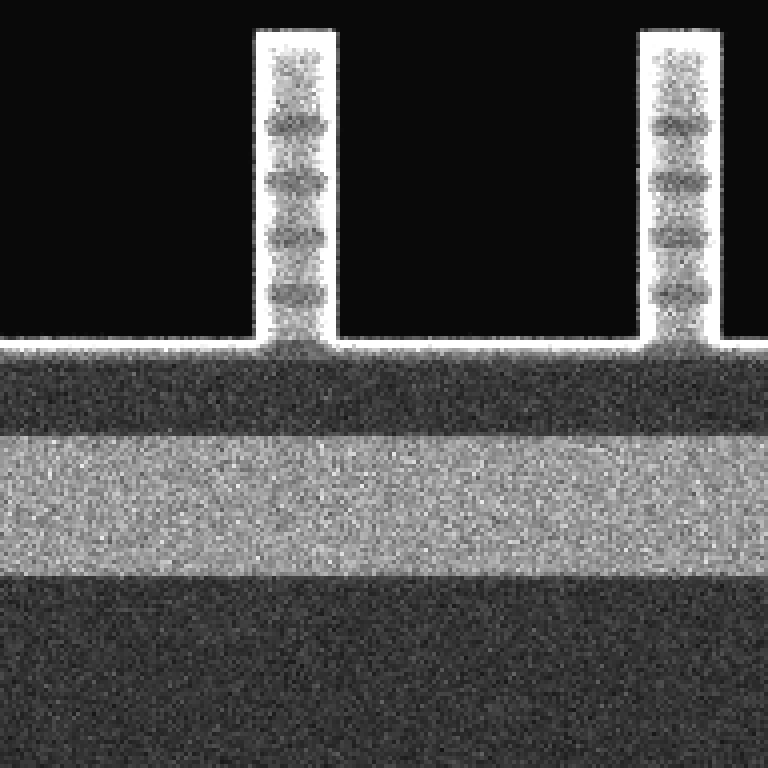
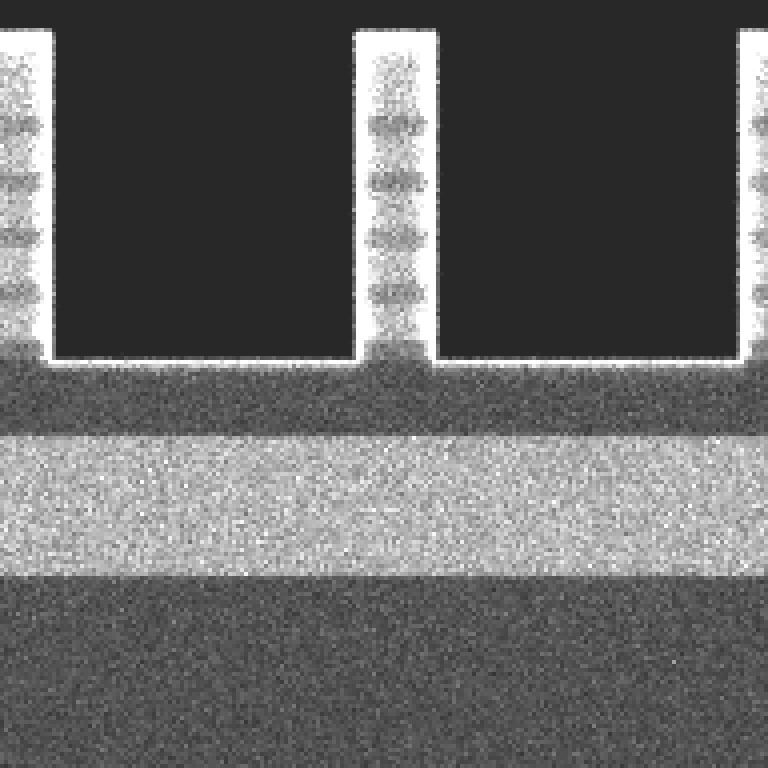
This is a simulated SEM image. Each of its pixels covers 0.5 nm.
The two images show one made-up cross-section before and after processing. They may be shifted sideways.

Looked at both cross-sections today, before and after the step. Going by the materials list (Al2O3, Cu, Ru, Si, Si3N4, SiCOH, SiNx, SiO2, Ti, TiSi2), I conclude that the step removed SiNx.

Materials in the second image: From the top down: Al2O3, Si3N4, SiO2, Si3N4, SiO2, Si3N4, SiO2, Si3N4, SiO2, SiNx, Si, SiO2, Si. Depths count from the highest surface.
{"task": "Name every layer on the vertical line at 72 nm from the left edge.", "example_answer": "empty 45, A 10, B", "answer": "empty 164, Si 38, SiO2 70, Si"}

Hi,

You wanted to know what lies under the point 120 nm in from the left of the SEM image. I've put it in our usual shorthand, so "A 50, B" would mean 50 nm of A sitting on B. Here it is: empty 164, Si 38, SiO2 70, Si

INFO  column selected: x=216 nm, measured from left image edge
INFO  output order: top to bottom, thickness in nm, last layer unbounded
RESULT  Al2O3 42, Si3N4 10, SiO2 18, Si3N4 10, SiO2 18, Si3N4 10, SiO2 18, Si3N4 10, SiO2 18, SiNx 10, Si 38, SiO2 70, Si